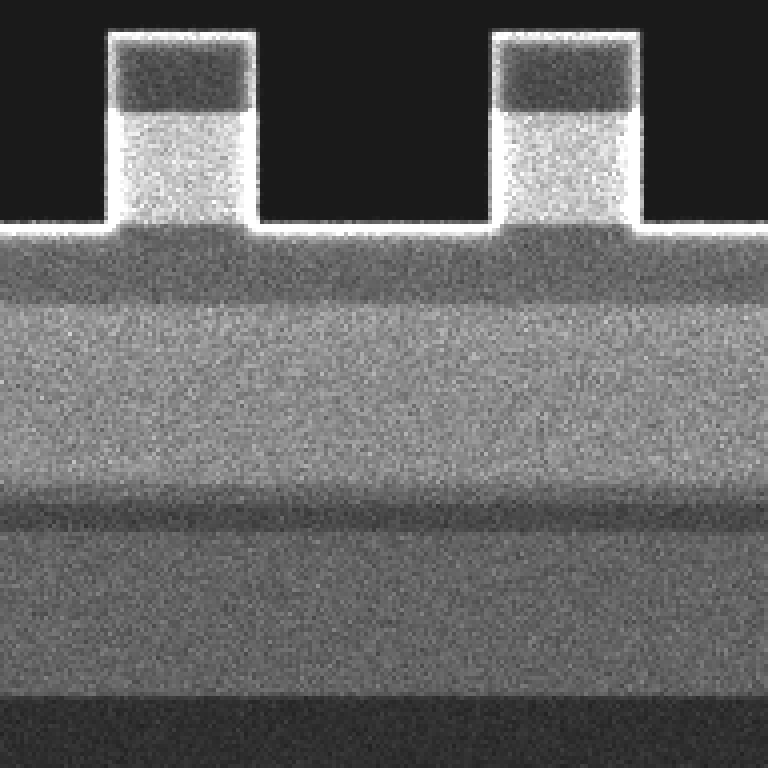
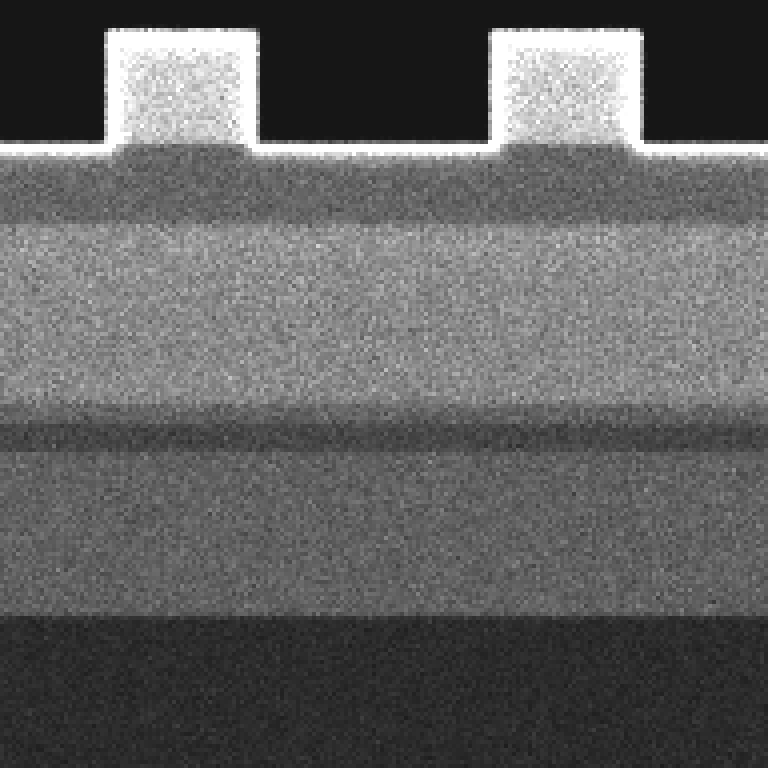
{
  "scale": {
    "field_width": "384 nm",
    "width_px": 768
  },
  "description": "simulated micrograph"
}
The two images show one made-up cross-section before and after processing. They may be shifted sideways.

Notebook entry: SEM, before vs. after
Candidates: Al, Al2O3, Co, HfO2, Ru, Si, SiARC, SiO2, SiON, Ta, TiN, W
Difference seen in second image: SiARC removed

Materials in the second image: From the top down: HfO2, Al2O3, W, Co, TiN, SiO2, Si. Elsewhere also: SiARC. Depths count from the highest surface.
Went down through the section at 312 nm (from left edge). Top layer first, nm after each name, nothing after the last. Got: HfO2 56, Al2O3 40, W 90, Co 10, TiN 14, SiO2 82, Si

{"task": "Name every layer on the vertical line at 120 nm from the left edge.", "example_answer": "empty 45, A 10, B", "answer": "HfO2 56, Al2O3 40, W 90, Co 10, TiN 14, SiO2 82, Si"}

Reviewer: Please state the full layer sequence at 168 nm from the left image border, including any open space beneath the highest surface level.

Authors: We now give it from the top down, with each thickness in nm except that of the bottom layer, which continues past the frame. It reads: empty 56, Al2O3 40, W 90, Co 10, TiN 14, SiO2 82, Si